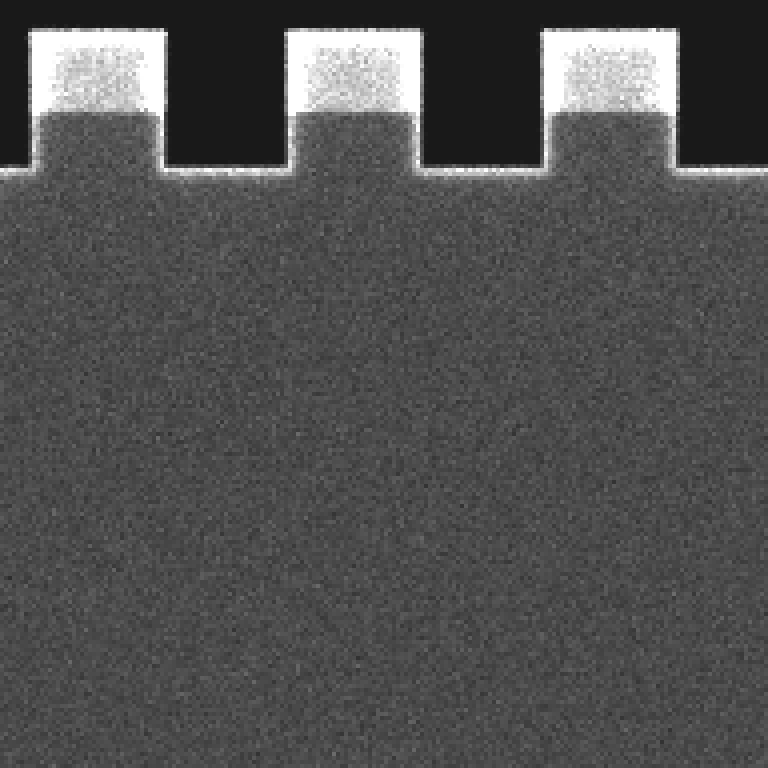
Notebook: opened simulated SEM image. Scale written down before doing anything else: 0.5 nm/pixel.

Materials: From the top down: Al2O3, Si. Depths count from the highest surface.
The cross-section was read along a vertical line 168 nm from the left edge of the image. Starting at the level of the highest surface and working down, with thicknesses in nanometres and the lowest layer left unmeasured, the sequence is Al2O3 40, Si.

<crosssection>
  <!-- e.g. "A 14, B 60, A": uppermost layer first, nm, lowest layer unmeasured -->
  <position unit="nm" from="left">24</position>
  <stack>Al2O3 40, Si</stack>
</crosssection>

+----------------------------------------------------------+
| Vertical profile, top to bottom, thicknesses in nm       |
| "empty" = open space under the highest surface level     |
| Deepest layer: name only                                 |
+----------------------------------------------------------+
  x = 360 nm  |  empty 68, Si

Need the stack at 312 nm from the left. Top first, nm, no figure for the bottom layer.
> Al2O3 40, Si